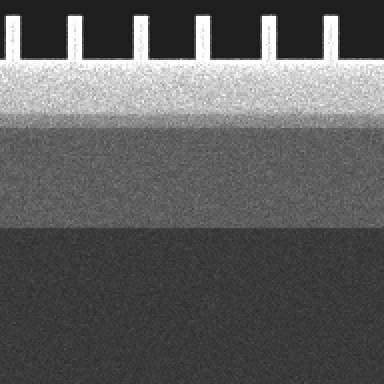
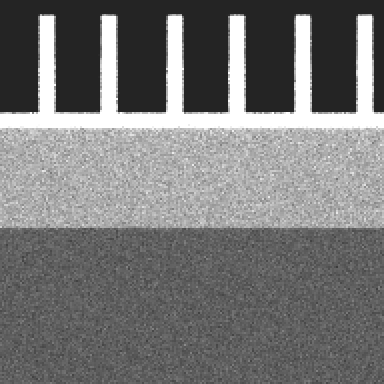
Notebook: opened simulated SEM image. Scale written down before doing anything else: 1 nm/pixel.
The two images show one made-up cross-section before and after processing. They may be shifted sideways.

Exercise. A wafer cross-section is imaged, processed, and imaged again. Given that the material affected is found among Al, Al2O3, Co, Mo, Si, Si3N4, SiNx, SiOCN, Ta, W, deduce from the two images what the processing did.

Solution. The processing removed W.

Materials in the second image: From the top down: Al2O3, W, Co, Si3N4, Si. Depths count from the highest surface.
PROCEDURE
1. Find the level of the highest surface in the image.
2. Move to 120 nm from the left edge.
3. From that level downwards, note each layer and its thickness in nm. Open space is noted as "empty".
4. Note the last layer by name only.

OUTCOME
empty 98, Co 14, Si3N4 100, Si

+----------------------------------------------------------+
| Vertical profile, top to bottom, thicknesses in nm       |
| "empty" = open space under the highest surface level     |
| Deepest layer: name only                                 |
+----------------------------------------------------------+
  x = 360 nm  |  Al2O3 44, W 54, Co 14, Si3N4 100, Si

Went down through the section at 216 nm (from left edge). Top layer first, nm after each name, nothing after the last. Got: empty 98, Co 14, Si3N4 100, Si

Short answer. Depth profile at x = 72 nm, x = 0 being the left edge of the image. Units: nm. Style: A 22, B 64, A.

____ empty 98, Co 14, Si3N4 100, Si